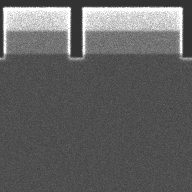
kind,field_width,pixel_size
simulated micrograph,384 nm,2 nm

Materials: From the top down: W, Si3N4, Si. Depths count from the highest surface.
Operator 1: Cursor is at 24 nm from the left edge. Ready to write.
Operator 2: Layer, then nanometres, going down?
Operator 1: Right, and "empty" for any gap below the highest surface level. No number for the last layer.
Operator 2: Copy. W 46, Si3N4 46, Si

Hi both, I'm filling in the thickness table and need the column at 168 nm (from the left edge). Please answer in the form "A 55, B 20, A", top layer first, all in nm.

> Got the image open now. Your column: W 46, Si3N4 46, Si